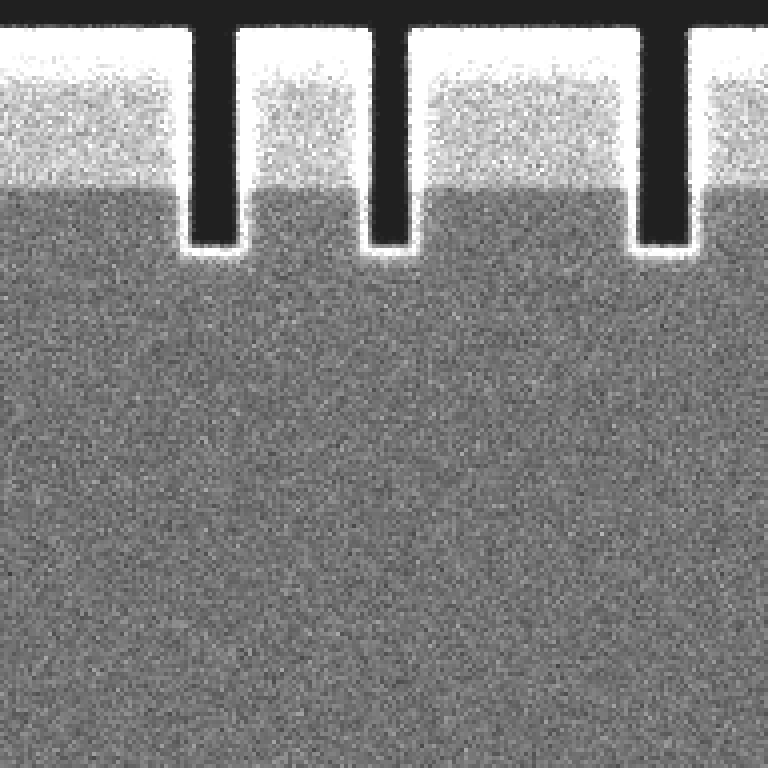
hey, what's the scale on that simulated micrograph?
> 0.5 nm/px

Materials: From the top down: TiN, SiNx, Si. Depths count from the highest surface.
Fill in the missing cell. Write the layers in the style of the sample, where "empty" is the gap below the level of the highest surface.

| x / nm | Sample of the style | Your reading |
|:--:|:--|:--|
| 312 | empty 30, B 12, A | TiN 24, SiNx 54, Si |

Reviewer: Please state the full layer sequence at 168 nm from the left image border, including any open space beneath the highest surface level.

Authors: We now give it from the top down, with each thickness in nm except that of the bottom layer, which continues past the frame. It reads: TiN 24, SiNx 54, Si